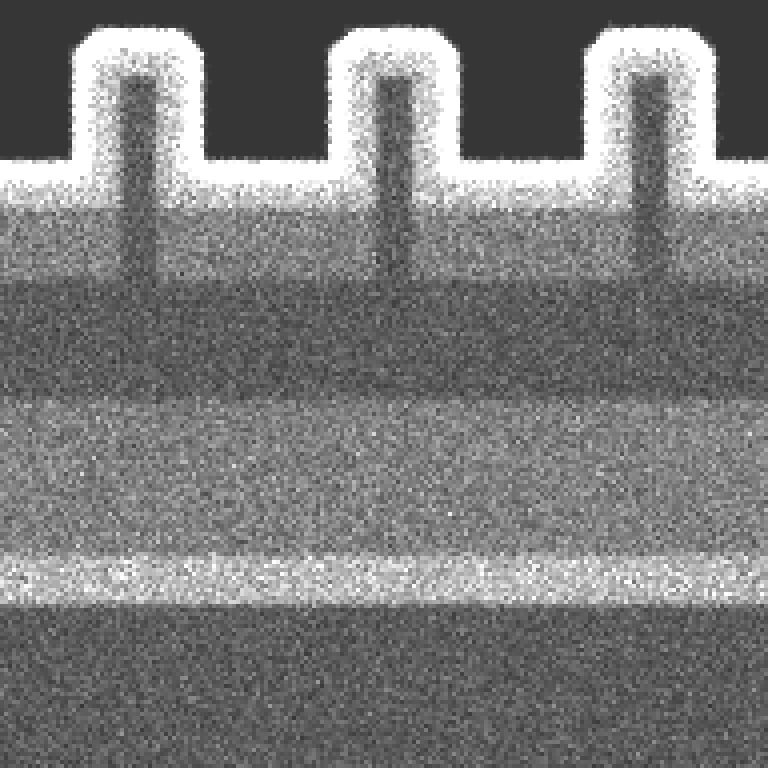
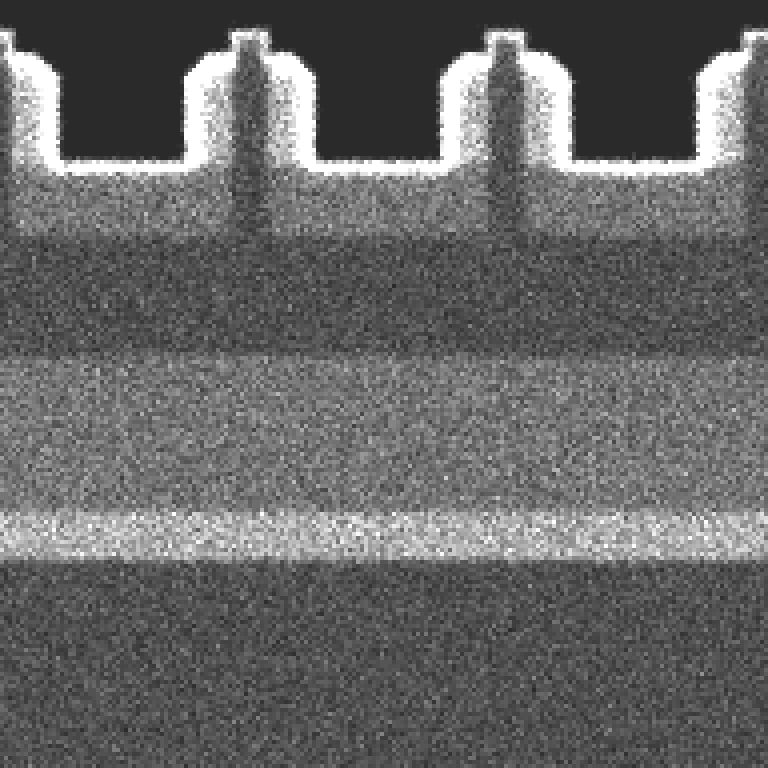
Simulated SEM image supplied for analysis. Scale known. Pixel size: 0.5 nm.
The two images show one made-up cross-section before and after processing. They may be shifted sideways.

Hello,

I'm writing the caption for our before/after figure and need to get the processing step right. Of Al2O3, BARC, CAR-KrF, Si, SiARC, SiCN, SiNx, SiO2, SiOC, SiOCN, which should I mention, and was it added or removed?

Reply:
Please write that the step removed Al2O3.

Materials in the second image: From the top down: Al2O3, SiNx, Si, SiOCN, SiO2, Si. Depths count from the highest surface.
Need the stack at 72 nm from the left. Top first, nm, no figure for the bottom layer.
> empty 66, SiNx 36, Si 60, SiOCN 78, SiO2 24, Si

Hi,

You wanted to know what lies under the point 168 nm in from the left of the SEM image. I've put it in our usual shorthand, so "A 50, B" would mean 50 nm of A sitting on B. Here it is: empty 66, SiNx 36, Si 60, SiOCN 78, SiO2 24, Si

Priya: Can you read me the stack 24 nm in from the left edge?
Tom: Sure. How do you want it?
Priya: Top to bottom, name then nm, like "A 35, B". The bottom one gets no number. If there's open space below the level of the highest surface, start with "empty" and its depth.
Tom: empty 20, Al2O3 46, SiNx 36, Si 60, SiOCN 78, SiO2 24, Si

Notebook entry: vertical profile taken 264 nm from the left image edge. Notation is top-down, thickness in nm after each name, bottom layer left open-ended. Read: empty 12, Al2O3 54, SiNx 36, Si 60, SiOCN 78, SiO2 24, Si